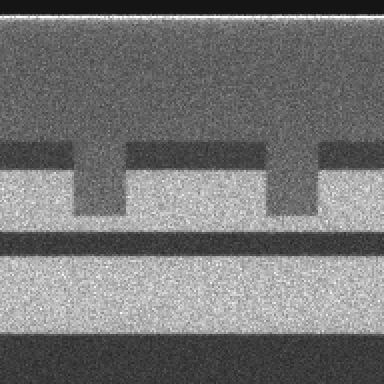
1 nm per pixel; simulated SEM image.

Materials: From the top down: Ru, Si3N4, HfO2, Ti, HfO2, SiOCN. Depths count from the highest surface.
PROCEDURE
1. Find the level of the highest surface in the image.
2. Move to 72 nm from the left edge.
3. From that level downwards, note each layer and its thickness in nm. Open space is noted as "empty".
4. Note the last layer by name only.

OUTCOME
Ru 126, Si3N4 28, HfO2 62, Ti 24, HfO2 78, SiOCN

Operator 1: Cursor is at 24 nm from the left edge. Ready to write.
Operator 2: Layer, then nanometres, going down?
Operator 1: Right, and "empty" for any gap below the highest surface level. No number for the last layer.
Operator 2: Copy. Ru 126, Si3N4 28, HfO2 62, Ti 24, HfO2 78, SiOCN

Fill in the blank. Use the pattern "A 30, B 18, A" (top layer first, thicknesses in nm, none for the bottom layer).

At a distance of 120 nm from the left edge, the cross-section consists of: Ru 200, HfO2 16, Ti 24, HfO2 78, SiOCN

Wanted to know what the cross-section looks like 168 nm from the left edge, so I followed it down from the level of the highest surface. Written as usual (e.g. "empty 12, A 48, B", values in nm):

Ru 126, Si3N4 28, HfO2 62, Ti 24, HfO2 78, SiOCN